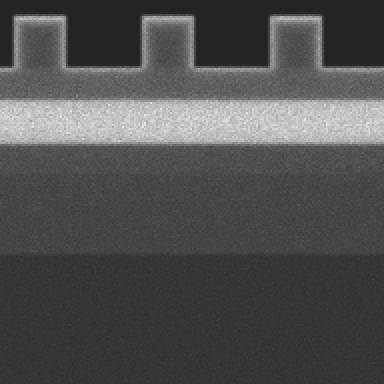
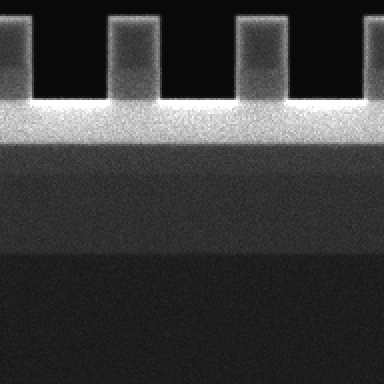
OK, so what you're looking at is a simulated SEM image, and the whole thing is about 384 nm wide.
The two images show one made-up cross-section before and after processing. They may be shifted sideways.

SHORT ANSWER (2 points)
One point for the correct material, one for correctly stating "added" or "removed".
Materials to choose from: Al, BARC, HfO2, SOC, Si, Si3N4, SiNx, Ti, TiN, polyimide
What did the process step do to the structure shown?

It removed TiN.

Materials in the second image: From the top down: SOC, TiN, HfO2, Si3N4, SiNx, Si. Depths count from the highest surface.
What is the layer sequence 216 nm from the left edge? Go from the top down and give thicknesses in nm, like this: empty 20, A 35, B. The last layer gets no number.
empty 84, HfO2 44, Si3N4 30, SiNx 80, Si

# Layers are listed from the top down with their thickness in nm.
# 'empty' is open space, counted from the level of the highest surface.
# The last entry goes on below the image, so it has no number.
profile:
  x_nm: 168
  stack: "empty 84, HfO2 44, Si3N4 30, SiNx 80, Si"